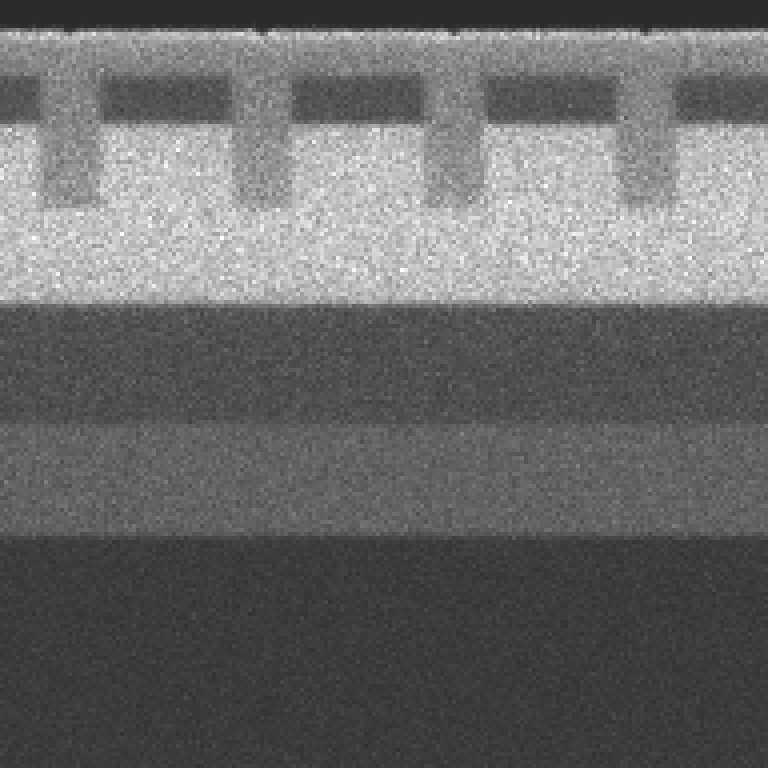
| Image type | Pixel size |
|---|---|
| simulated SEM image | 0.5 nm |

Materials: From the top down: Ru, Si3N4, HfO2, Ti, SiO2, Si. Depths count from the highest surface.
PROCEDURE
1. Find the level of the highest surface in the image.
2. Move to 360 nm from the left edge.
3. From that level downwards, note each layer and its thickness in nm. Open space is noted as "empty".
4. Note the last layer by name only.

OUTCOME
Ru 22, Si3N4 24, HfO2 90, Ti 60, SiO2 56, Si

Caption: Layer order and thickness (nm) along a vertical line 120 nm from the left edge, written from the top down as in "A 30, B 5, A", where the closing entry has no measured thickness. Ru 88, HfO2 48, Ti 60, SiO2 56, Si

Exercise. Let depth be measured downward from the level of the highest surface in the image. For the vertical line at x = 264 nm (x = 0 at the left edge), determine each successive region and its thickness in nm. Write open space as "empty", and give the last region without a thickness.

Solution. Ru 22, Si3N4 24, HfO2 90, Ti 60, SiO2 56, Si